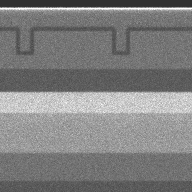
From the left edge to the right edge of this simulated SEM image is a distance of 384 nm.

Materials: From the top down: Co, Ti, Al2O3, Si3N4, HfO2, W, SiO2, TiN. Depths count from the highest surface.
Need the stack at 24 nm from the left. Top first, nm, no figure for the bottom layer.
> Co 38, Ti 8, Al2O3 76, Si3N4 46, HfO2 42, W 80, SiO2 56, TiN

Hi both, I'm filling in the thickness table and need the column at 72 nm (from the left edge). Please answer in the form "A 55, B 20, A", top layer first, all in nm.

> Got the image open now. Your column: Co 38, Ti 8, Al2O3 76, Si3N4 46, HfO2 42, W 80, SiO2 56, TiN